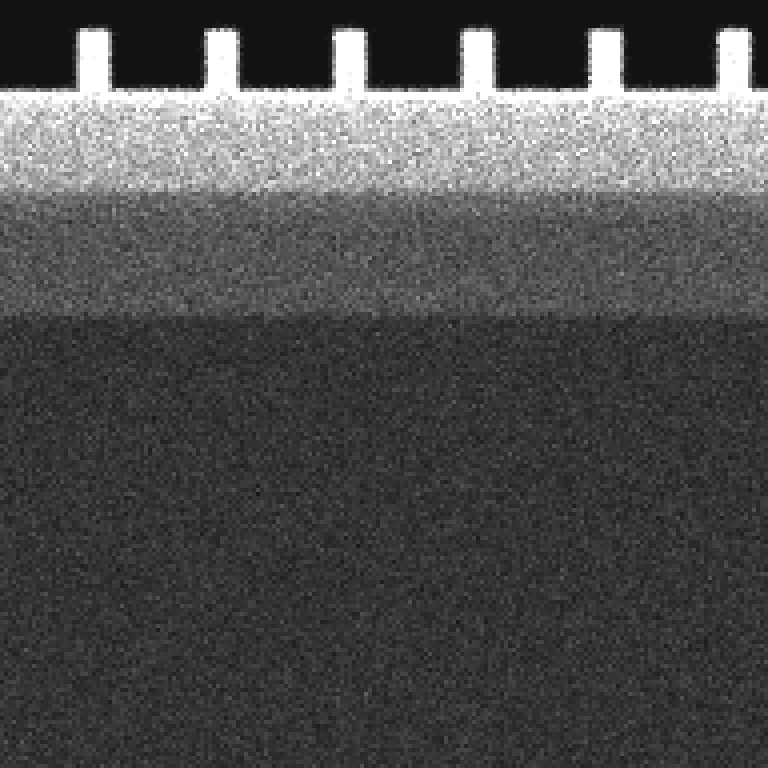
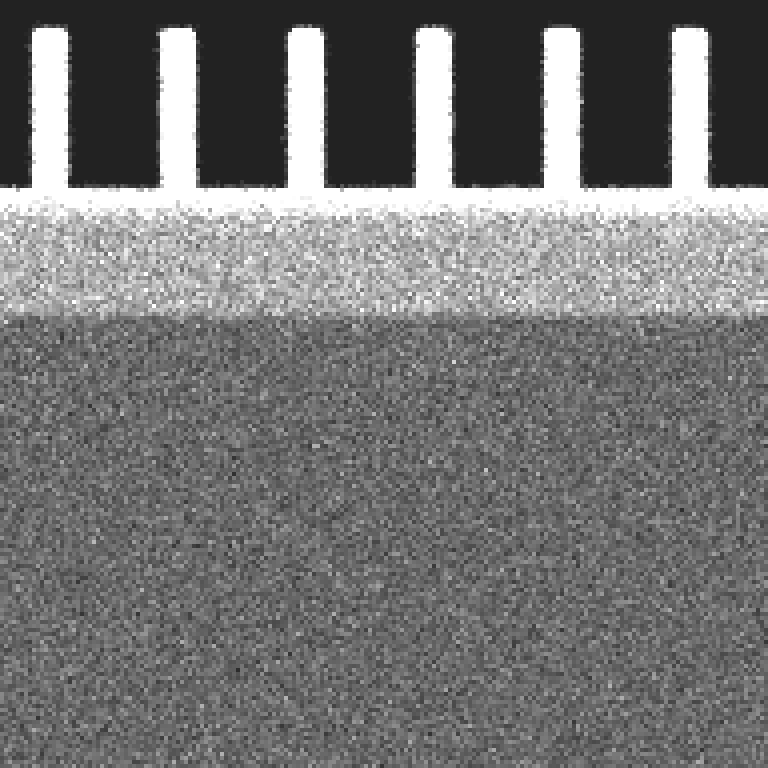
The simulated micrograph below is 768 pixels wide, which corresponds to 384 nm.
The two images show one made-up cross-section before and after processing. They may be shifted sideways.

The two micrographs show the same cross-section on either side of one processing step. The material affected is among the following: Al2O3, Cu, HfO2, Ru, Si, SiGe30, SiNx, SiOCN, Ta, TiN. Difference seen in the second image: Ru removed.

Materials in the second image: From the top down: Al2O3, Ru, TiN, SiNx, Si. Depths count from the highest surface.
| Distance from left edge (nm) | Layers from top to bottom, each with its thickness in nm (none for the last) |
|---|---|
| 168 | empty 80, TiN 12, SiNx 50, Si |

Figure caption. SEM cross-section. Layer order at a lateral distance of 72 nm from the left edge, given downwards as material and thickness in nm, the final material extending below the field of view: empty 80, TiN 12, SiNx 50, Si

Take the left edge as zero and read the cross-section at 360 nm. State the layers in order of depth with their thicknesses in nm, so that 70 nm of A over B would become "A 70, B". empty 80, TiN 12, SiNx 50, Si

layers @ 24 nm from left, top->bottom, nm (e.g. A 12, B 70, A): Al2O3 30, Ru 50, TiN 12, SiNx 50, Si